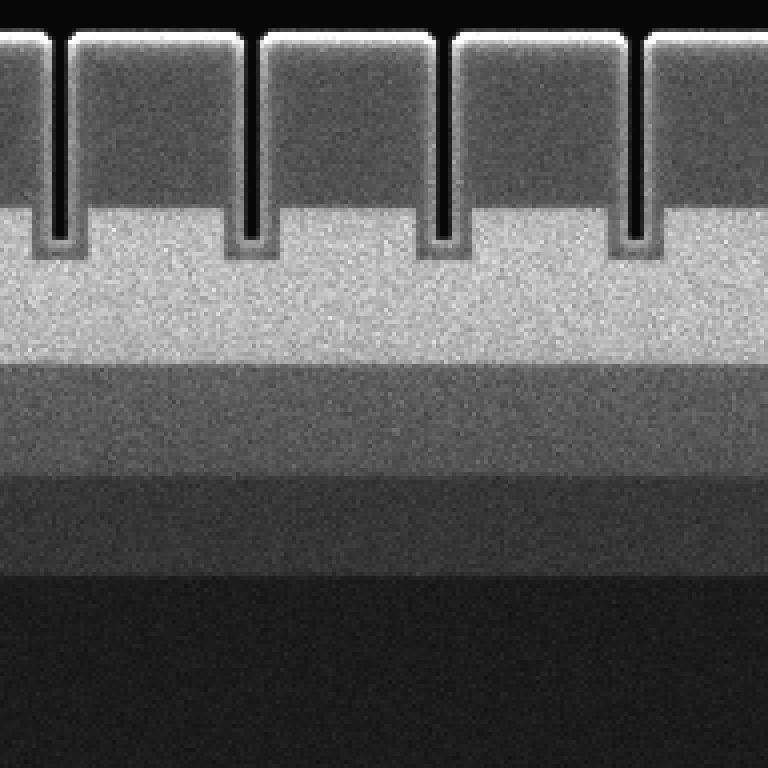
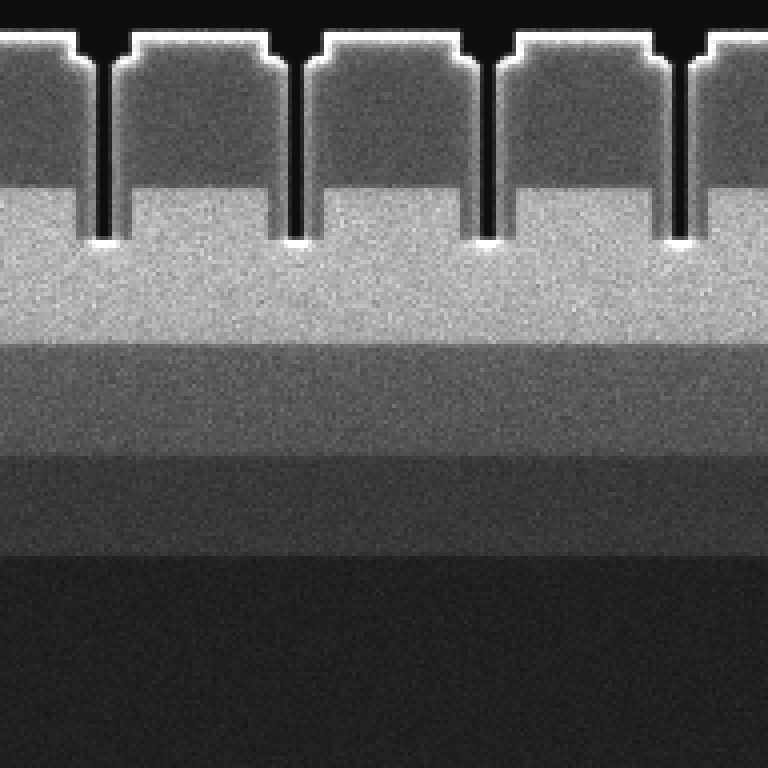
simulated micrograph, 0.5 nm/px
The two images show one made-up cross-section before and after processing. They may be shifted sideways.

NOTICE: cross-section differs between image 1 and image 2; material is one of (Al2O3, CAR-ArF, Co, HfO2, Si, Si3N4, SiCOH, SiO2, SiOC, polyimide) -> removed: SiO2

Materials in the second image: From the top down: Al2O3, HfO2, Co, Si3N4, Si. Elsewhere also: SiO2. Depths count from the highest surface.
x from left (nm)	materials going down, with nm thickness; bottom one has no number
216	Al2O3 78, HfO2 78, Co 56, Si3N4 50, Si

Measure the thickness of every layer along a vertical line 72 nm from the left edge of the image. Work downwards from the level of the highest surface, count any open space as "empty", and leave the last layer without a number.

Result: Al2O3 78, HfO2 78, Co 56, Si3N4 50, Si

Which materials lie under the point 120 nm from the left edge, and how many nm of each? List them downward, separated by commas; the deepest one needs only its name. Al2O3 78, HfO2 78, Co 56, Si3N4 50, Si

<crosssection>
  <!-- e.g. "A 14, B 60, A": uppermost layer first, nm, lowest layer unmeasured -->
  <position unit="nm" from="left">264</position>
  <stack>Al2O3 78, HfO2 78, Co 56, Si3N4 50, Si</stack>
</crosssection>